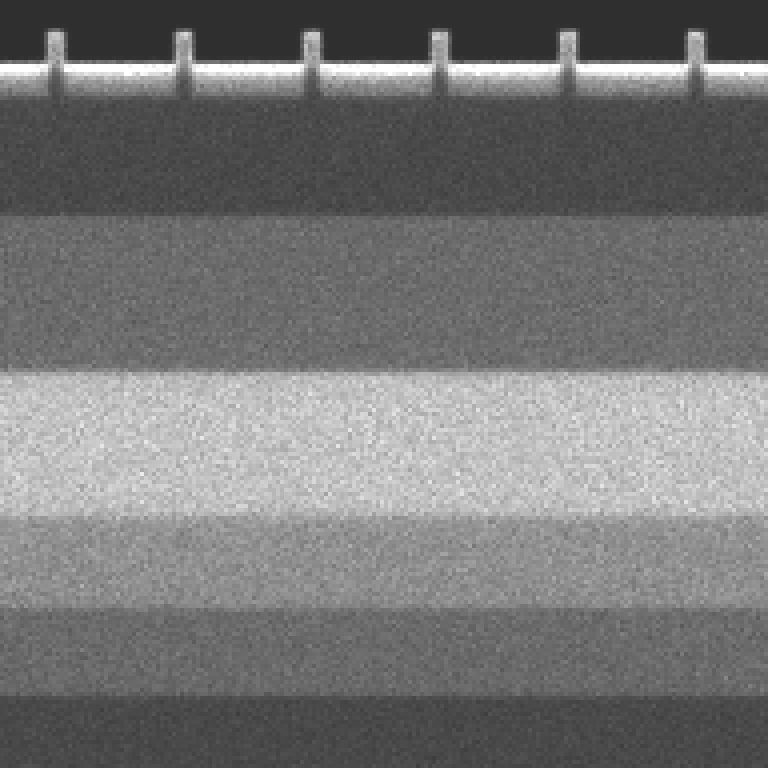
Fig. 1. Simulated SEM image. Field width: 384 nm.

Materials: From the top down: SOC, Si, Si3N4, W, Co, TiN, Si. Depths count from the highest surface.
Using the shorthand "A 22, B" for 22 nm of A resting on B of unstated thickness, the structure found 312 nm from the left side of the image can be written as empty 16, SOC 16, Si 60, Si3N4 78, W 72, Co 46, TiN 44, Si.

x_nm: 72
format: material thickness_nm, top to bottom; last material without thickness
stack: empty 16, SOC 16, Si 60, Si3N4 78, W 72, Co 46, TiN 44, Si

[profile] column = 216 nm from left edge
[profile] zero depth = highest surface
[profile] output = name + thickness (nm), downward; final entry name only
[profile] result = Si 92, Si3N4 78, W 72, Co 46, TiN 44, Si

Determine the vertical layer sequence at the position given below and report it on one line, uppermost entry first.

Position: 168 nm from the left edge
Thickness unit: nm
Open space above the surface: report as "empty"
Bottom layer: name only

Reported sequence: empty 16, SOC 16, Si 60, Si3N4 78, W 72, Co 46, TiN 44, Si